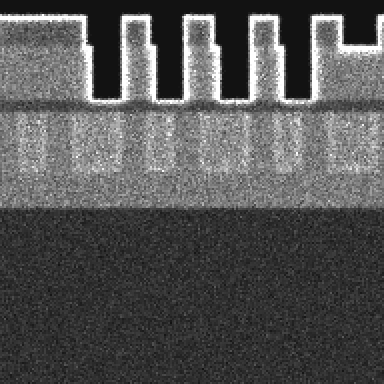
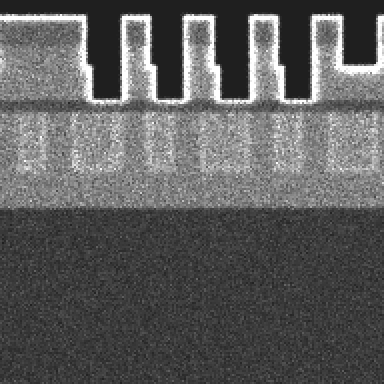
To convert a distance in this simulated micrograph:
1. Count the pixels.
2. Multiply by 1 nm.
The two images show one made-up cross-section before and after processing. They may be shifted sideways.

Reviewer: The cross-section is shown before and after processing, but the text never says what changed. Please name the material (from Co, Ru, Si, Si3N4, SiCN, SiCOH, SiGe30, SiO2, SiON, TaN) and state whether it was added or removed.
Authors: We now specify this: SiO2, removed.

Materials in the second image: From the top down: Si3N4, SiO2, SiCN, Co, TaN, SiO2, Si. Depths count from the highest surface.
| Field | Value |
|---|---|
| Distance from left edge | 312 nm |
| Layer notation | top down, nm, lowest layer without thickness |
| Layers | Si3N4 30, SiO2 54, SiCN 12, SiO2 96, Si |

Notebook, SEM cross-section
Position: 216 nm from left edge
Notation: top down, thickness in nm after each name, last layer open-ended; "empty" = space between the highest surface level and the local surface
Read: empty 50, SiO2 34, SiCN 12, Co 54, TaN 6, SiO2 36, Si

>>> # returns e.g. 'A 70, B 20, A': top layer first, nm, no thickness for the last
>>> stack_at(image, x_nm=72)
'Si3N4 30, SiO2 54, SiCN 12, TaN 60, SiO2 36, Si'